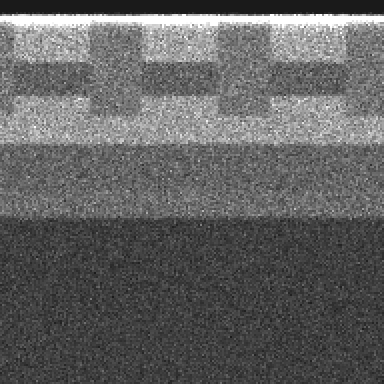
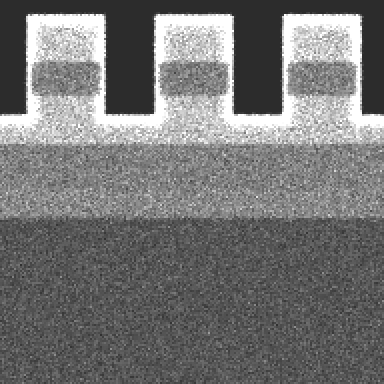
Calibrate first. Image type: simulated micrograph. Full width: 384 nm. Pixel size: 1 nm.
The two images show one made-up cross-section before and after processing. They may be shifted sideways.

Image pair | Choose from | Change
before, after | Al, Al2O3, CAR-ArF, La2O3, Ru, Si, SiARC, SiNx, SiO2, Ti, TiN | SiARC (removed)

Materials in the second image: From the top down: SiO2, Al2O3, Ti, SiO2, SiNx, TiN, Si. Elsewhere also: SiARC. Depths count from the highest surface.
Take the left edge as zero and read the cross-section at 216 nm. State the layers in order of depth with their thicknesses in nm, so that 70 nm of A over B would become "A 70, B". SiO2 14, Al2O3 32, Ti 34, SiO2 48, SiNx 46, TiN 28, Si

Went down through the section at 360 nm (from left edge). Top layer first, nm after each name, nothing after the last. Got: empty 100, SiO2 28, SiNx 46, TiN 28, Si